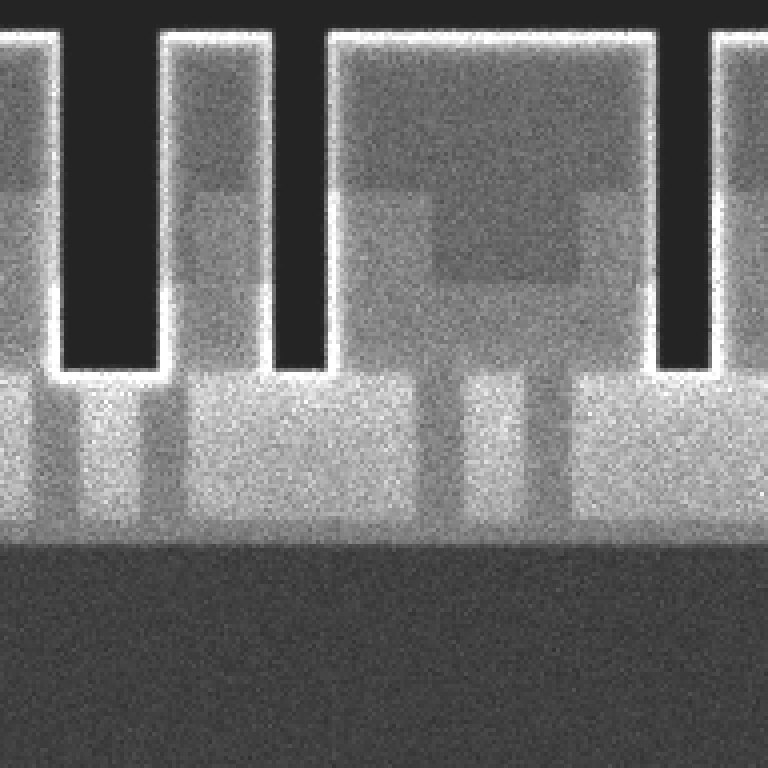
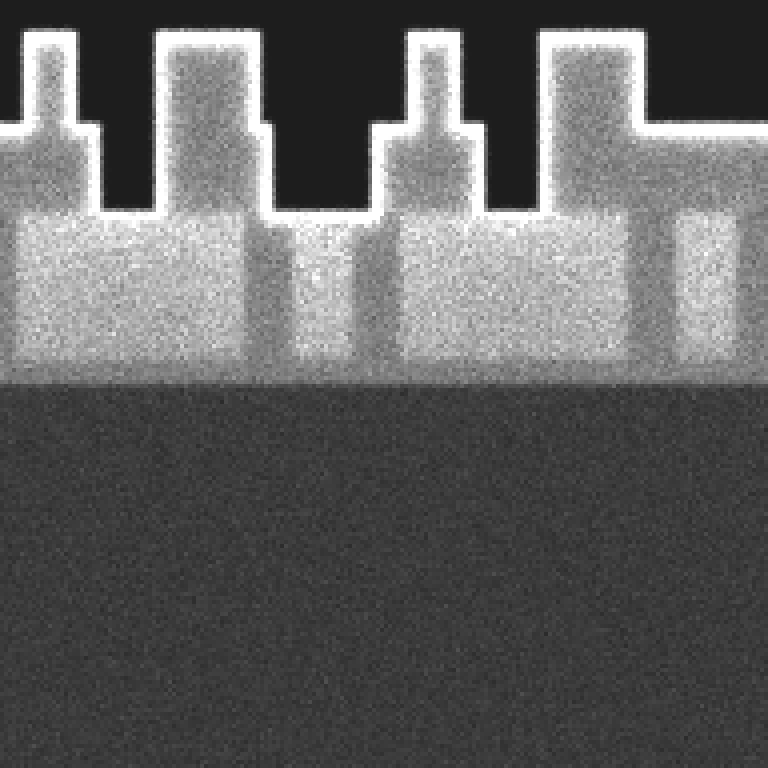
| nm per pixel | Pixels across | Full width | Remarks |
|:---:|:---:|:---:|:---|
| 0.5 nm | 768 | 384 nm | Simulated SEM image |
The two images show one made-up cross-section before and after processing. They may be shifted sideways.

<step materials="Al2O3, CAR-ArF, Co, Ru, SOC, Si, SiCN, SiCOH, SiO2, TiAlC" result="removed SOC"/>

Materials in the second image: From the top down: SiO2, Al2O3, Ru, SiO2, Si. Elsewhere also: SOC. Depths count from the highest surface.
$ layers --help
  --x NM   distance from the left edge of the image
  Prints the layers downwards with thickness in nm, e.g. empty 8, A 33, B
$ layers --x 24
SiO2 76, Al2O3 14, Ru 74, SiO2 12, Si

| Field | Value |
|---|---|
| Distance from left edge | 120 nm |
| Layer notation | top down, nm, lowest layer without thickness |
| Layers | SiO2 76, Al2O3 14, Ru 74, SiO2 12, Si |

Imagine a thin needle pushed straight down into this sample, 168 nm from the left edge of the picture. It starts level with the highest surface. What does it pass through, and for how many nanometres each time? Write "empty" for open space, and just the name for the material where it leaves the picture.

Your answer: empty 90, Ru 74, SiO2 12, Si